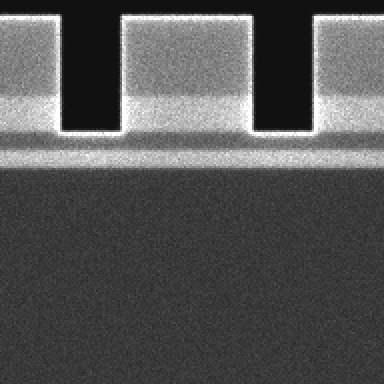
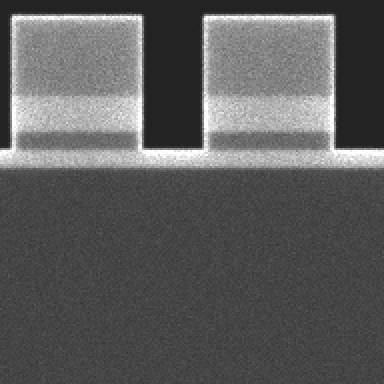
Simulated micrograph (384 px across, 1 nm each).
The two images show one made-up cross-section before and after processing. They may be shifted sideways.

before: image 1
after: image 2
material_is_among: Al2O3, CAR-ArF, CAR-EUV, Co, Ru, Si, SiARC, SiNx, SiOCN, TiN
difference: SiNx, removed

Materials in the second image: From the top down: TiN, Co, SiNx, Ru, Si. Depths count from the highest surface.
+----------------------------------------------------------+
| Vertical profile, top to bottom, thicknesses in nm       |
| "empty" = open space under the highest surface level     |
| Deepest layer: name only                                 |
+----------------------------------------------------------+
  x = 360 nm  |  empty 134, Ru 18, Si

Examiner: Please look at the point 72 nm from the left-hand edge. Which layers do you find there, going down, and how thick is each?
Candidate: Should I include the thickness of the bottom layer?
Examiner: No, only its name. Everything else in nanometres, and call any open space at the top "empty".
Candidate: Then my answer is TiN 80, Co 36, SiNx 18, Ru 18, Si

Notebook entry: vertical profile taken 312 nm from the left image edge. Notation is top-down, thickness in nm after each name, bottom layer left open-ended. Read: TiN 80, Co 36, SiNx 18, Ru 18, Si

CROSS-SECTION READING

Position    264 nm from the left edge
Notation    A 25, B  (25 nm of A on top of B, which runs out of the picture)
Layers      TiN 80, Co 36, SiNx 18, Ru 18, Si